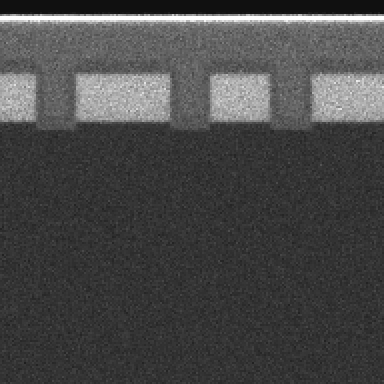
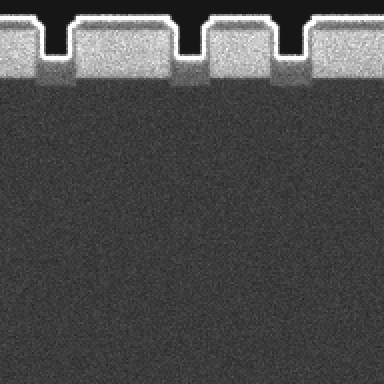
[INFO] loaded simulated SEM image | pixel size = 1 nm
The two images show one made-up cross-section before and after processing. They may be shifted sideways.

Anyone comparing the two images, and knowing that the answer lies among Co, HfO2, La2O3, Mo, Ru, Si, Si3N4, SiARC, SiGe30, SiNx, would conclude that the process removed Si3N4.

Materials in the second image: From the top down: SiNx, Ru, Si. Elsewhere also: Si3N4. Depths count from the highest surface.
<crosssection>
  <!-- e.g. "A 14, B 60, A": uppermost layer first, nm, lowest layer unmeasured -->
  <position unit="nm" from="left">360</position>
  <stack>SiNx 14, Ru 48, Si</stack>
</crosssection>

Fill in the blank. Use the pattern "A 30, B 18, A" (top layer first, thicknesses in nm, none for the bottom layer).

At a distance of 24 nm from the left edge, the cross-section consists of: SiNx 14, Ru 48, Si